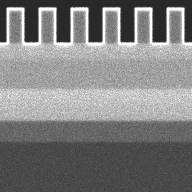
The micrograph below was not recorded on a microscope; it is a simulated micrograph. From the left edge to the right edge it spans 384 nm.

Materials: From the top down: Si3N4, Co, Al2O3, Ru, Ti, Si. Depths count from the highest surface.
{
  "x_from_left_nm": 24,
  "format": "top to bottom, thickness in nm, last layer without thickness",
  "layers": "Si3N4 70, Co 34, Al2O3 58, Ru 64, Ti 42, Si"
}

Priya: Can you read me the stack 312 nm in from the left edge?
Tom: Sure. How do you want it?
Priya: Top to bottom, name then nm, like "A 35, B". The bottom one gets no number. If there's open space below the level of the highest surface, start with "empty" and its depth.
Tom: empty 70, Co 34, Al2O3 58, Ru 64, Ti 42, Si